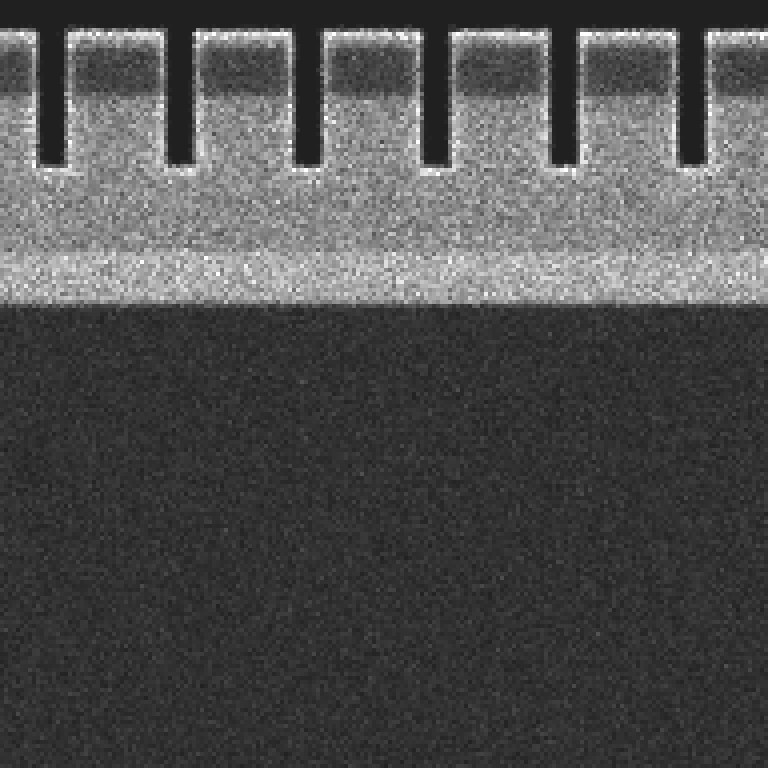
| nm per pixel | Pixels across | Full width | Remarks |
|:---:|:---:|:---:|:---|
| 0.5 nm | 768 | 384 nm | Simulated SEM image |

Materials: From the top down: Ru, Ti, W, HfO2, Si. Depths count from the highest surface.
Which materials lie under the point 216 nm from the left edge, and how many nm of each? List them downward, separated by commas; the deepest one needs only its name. empty 68, W 42, HfO2 26, Si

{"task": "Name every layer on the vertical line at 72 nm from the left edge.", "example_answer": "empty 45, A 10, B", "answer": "Ru 8, Ti 24, W 78, HfO2 26, Si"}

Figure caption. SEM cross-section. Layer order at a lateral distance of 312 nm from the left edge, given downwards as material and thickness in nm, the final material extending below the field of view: Ru 8, Ti 24, W 78, HfO2 26, Si